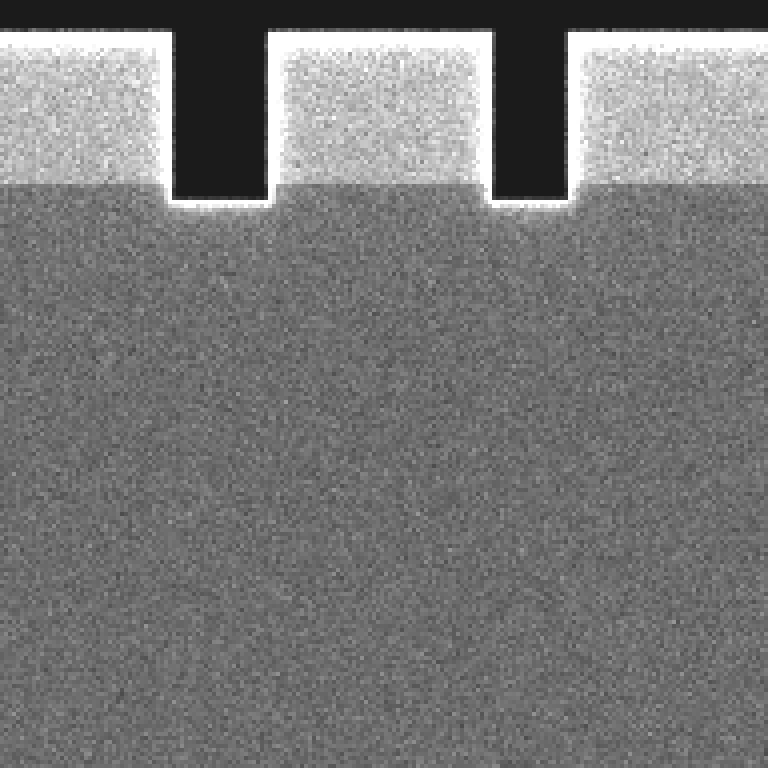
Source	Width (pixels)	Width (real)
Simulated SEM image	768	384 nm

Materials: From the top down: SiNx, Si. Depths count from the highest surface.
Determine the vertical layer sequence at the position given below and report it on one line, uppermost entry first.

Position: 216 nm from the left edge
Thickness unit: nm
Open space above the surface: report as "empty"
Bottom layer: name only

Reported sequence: SiNx 76, Si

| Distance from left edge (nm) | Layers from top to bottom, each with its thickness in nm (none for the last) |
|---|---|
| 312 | SiNx 76, Si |